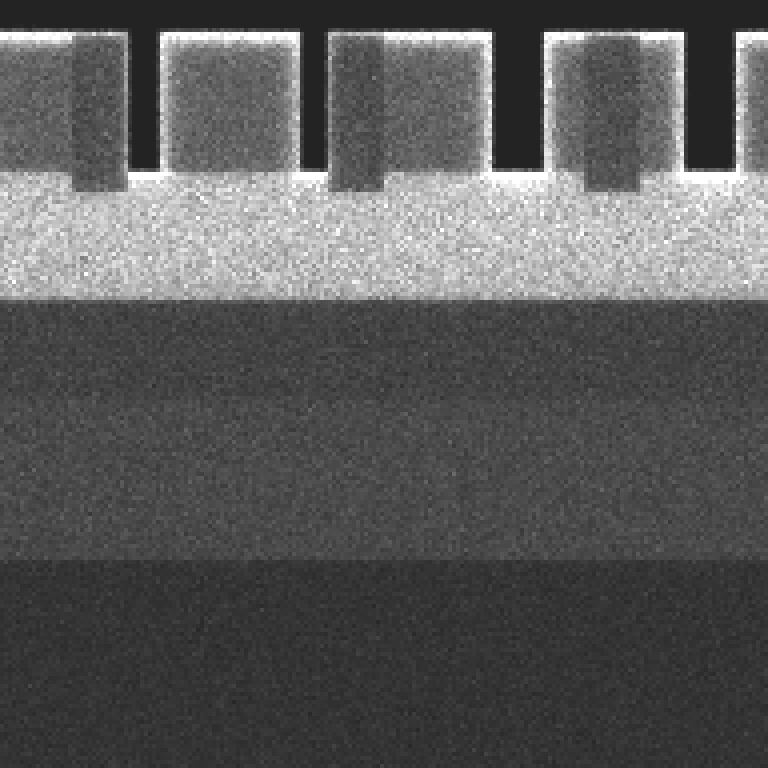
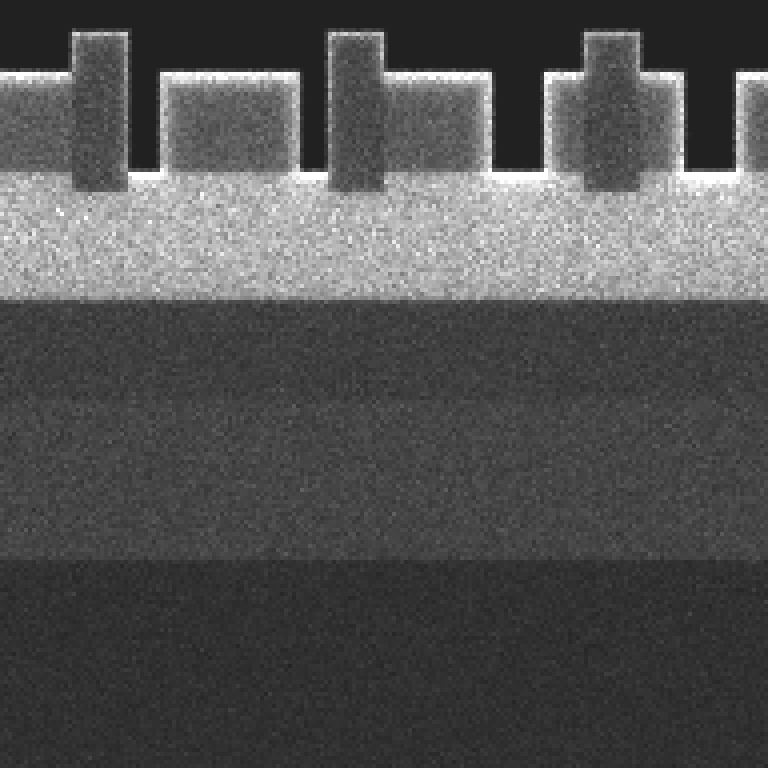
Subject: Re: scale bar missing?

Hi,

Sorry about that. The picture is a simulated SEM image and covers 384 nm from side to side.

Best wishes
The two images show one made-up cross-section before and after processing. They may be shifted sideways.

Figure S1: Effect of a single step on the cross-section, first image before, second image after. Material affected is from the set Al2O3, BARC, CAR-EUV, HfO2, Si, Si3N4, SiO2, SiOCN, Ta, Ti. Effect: removed Al2O3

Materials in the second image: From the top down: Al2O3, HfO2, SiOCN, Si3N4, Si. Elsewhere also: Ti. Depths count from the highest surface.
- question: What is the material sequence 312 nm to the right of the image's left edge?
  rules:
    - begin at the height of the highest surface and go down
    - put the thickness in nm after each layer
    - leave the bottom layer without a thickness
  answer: Ti 80, HfO2 54, SiOCN 50, Si3N4 80, Si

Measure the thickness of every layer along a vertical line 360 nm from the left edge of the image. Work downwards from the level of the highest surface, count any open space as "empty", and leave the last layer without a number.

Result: empty 70, HfO2 64, SiOCN 50, Si3N4 80, Si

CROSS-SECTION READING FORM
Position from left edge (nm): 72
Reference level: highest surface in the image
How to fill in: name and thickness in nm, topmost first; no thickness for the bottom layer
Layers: empty 70, HfO2 64, SiOCN 50, Si3N4 80, Si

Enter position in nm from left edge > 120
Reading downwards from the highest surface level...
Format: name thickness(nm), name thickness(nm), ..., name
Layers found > empty 20, Al2O3 50, HfO2 64, SiOCN 50, Si3N4 80, Si